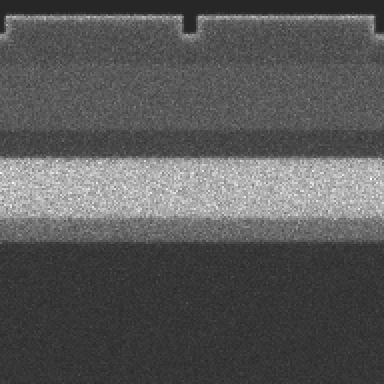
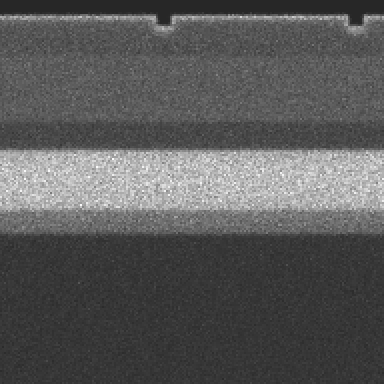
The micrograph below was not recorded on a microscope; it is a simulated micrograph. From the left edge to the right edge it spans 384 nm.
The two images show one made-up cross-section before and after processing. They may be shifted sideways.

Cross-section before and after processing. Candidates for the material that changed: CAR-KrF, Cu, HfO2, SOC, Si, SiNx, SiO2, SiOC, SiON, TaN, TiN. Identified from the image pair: TiN (removed).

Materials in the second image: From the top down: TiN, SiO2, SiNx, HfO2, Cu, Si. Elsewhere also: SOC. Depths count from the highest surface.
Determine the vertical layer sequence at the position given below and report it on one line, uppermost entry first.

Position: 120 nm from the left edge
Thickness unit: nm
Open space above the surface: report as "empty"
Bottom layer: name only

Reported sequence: TiN 40, SiO2 66, SiNx 28, HfO2 60, Cu 24, Si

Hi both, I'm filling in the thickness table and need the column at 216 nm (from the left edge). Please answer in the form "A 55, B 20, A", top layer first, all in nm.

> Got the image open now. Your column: TiN 40, SiO2 66, SiNx 28, HfO2 60, Cu 24, Si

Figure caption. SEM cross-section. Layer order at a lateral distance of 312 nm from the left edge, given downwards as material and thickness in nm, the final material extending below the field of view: TiN 40, SiO2 66, SiNx 28, HfO2 60, Cu 24, Si